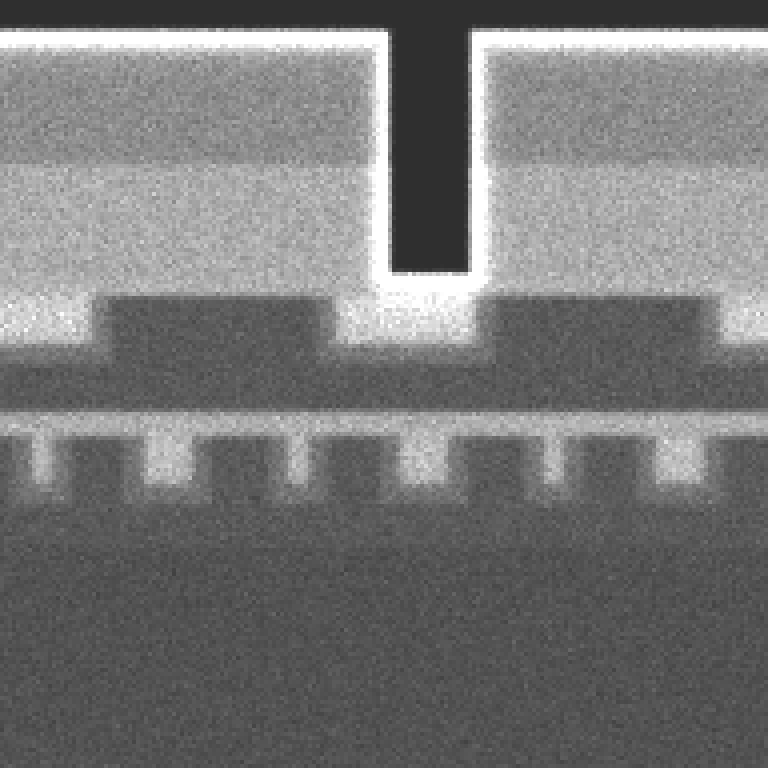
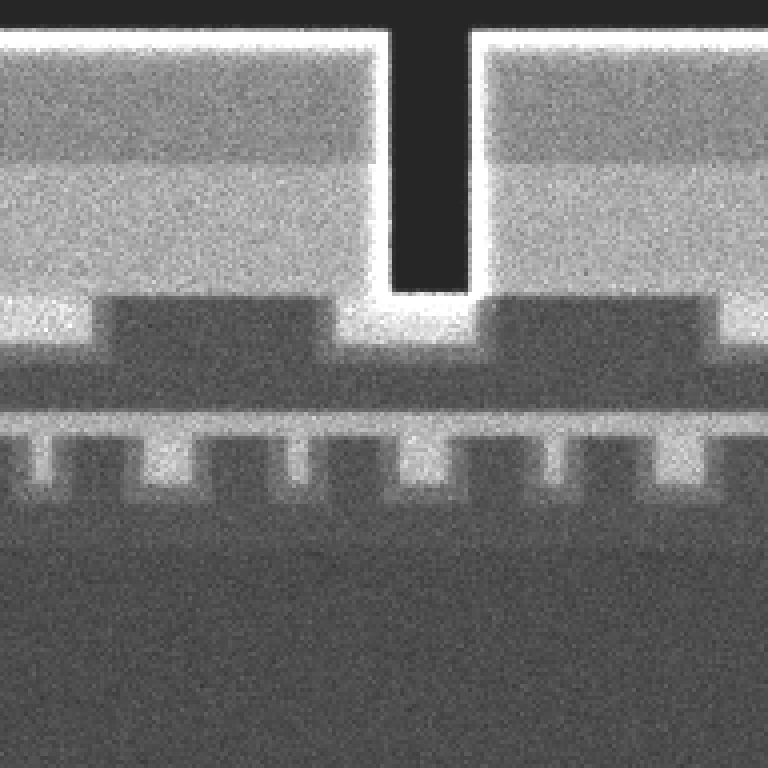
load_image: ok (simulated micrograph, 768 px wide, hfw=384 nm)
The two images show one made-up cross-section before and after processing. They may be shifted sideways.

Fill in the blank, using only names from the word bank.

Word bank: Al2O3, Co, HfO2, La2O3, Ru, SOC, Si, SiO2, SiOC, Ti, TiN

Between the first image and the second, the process removed Al2O3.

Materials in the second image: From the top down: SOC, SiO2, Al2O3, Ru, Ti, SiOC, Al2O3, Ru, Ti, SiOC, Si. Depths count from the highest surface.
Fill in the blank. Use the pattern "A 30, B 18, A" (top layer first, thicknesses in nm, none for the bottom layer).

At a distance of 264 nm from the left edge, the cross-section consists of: SOC 66, SiO2 56, Al2O3 10, SiOC 58, Al2O3 12, Ti 34, SiOC 22, Si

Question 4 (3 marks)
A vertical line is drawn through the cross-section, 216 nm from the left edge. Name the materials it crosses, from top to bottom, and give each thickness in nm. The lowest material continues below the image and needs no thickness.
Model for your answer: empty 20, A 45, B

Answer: empty 132, Ru 24, Ti 10, SiOC 24, Al2O3 12, Ru 24, Ti 10, SiOC 22, Si